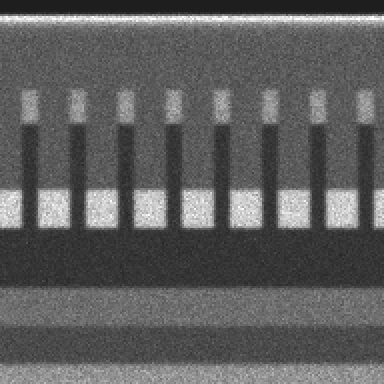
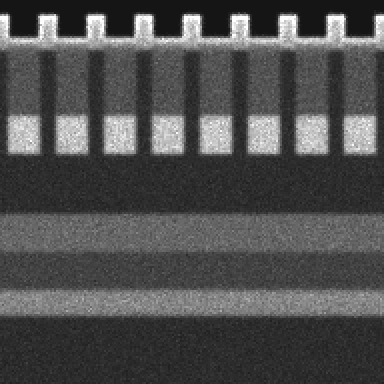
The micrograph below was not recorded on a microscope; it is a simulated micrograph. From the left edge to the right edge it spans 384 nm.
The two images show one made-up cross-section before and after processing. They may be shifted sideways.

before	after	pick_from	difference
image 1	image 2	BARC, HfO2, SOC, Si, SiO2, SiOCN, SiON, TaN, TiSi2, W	SOC removed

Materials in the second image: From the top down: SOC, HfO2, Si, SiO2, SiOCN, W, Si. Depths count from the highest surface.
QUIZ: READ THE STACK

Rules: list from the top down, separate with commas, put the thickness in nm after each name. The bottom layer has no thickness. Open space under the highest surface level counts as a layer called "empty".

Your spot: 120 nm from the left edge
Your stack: empty 22, SOC 78, HfO2 38, Si 60, SiO2 38, SiOCN 38, W 26, Si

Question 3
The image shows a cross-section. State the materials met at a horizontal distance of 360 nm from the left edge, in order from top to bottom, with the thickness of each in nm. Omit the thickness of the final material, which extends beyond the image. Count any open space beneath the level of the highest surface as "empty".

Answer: empty 22, SOC 78, HfO2 38, Si 60, SiO2 38, SiOCN 38, W 26, Si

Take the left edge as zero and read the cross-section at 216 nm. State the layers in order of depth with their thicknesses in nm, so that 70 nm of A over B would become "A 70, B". empty 22, SOC 78, HfO2 38, Si 60, SiO2 38, SiOCN 38, W 26, Si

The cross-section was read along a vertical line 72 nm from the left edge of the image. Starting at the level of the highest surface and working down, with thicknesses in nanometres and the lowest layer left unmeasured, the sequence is empty 22, SOC 78, HfO2 38, Si 60, SiO2 38, SiOCN 38, W 26, Si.